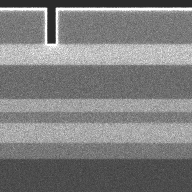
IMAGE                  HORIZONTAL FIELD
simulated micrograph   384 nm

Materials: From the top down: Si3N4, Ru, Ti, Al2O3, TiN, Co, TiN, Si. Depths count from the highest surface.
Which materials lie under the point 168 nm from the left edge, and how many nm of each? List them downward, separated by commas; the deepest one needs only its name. Si3N4 72, Ru 42, Ti 68, Al2O3 26, TiN 22, Co 40, TiN 32, Si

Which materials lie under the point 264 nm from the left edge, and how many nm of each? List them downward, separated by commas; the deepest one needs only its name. Si3N4 72, Ru 42, Ti 68, Al2O3 26, TiN 22, Co 40, TiN 32, Si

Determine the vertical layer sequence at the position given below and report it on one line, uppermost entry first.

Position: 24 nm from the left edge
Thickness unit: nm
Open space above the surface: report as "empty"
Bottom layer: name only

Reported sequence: Si3N4 72, Ru 42, Ti 68, Al2O3 26, TiN 22, Co 40, TiN 32, Si